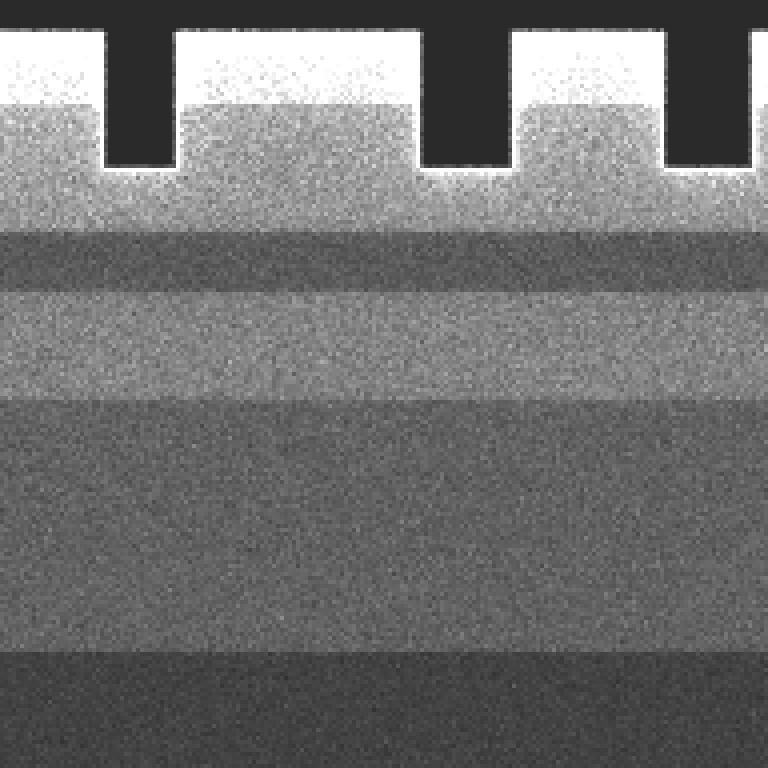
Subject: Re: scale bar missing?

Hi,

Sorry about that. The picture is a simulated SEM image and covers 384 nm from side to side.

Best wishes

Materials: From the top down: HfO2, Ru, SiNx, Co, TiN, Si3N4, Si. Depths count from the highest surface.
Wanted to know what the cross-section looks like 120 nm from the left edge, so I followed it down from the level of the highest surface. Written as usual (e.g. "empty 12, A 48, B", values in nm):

HfO2 36, Ru 64, SiNx 30, Co 54, TiN 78, Si3N4 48, Si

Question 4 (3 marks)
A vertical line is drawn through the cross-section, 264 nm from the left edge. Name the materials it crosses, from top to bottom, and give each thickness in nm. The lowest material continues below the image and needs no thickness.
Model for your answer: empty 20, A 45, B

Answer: HfO2 36, Ru 64, SiNx 30, Co 54, TiN 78, Si3N4 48, Si